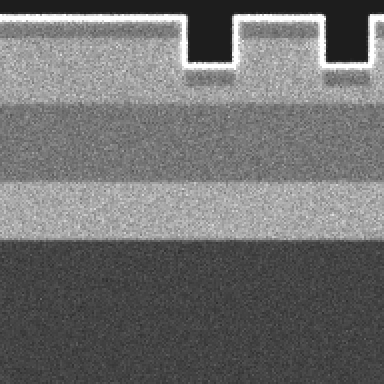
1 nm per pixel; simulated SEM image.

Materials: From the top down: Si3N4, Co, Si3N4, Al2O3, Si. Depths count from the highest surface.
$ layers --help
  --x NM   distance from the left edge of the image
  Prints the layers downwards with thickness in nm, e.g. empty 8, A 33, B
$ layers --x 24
Si3N4 22, Co 66, Si3N4 78, Al2O3 58, Si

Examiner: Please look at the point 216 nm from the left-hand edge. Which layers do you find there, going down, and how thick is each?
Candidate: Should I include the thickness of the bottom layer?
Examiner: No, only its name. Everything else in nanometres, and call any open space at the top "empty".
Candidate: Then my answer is empty 48, Si3N4 22, Co 18, Si3N4 78, Al2O3 58, Si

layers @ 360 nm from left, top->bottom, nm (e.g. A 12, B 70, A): empty 48, Si3N4 22, Co 18, Si3N4 78, Al2O3 58, Si